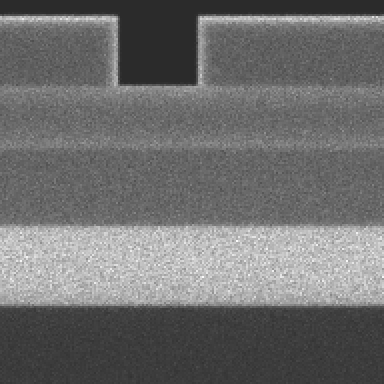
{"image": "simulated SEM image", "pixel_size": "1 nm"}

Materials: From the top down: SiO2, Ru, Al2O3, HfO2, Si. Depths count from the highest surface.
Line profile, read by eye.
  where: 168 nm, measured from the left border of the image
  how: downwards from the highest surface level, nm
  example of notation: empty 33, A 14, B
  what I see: empty 70, Ru 62, Al2O3 78, HfO2 80, Si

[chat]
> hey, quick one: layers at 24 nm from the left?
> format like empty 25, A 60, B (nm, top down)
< SiO2 70, Ru 62, Al2O3 78, HfO2 80, Si